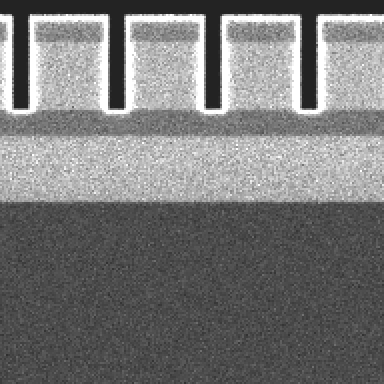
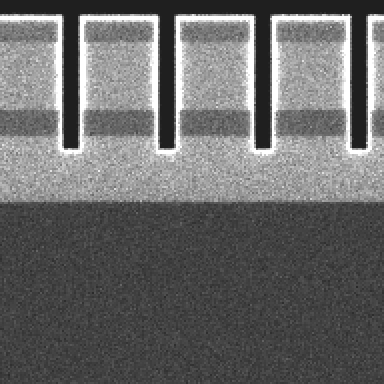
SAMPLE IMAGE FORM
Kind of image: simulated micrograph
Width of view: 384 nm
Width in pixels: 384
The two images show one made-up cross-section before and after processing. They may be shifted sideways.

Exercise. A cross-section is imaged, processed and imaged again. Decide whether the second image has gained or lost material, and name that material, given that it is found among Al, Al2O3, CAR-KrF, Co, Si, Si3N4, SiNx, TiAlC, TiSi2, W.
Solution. removed: Co and SiNx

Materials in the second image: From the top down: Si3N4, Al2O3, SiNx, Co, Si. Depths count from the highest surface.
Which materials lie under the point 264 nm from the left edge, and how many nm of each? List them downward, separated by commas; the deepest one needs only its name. empty 134, Co 52, Si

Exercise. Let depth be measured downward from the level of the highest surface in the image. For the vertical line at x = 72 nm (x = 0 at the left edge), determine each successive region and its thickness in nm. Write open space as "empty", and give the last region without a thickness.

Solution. empty 134, Co 52, Si